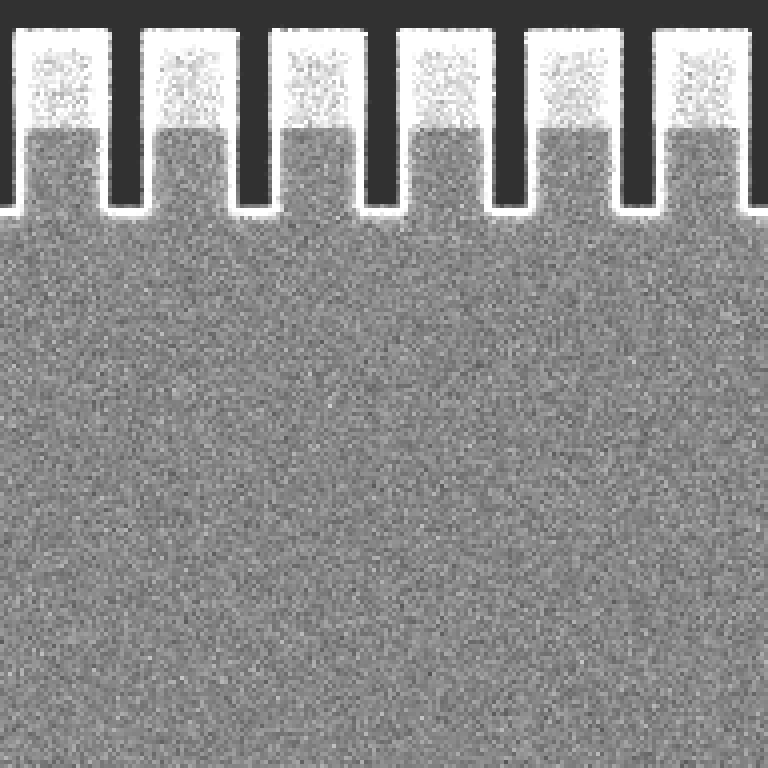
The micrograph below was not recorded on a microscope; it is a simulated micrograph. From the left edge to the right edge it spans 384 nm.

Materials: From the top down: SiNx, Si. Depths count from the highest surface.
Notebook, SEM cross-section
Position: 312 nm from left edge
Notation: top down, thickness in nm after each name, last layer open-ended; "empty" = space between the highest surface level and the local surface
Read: empty 88, Si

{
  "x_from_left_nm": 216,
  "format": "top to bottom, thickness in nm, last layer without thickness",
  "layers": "SiNx 48, Si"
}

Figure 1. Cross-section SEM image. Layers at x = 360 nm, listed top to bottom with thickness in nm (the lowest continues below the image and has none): SiNx 48, Si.